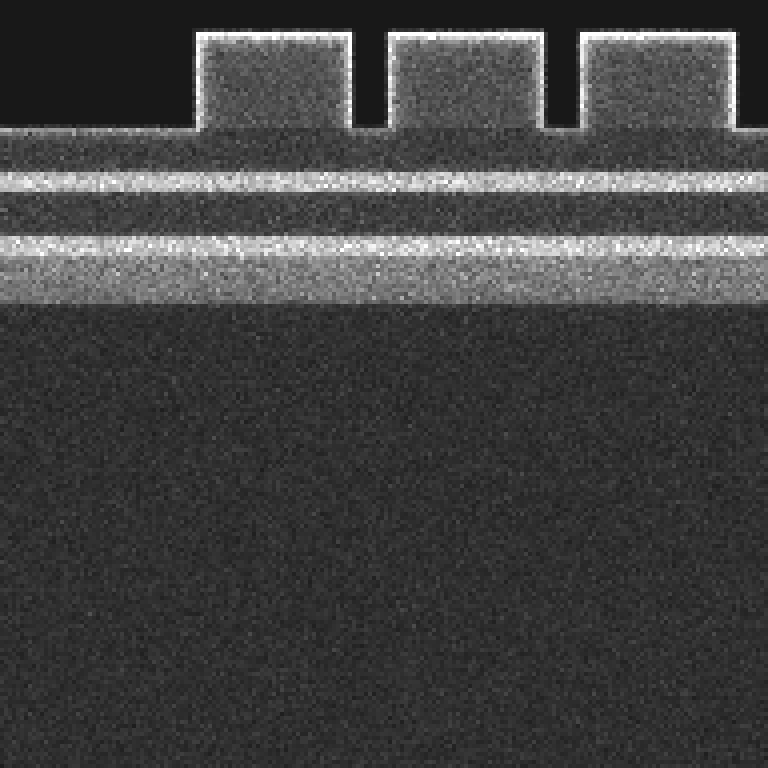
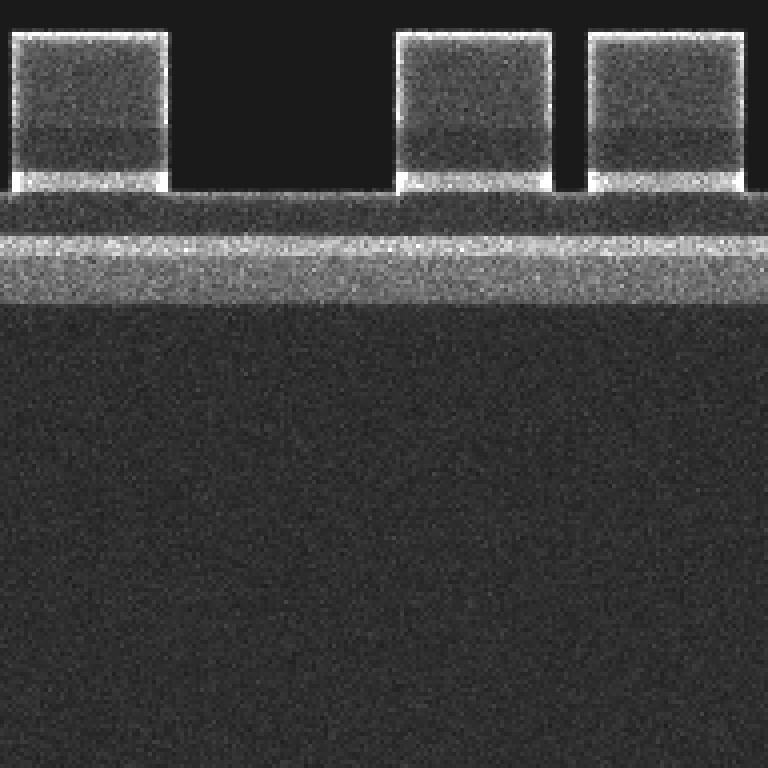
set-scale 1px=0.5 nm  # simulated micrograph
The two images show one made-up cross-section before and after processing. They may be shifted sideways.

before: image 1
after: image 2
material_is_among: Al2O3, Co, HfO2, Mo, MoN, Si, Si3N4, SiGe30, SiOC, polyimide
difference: HfO2 and SiGe30, removed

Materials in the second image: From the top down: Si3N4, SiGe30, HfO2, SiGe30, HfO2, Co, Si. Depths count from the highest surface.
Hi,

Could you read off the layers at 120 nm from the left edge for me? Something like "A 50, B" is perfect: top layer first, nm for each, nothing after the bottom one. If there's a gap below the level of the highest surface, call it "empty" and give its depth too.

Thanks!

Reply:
empty 80, SiGe30 22, HfO2 10, Co 24, Si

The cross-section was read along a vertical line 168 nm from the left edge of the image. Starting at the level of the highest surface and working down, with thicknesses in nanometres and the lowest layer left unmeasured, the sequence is empty 80, SiGe30 22, HfO2 10, Co 24, Si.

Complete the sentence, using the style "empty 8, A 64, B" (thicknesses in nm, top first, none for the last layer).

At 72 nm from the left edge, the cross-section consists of Si3N4 48, SiGe30 22, HfO2 10, SiGe30 22, HfO2 10, Co 24, Si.